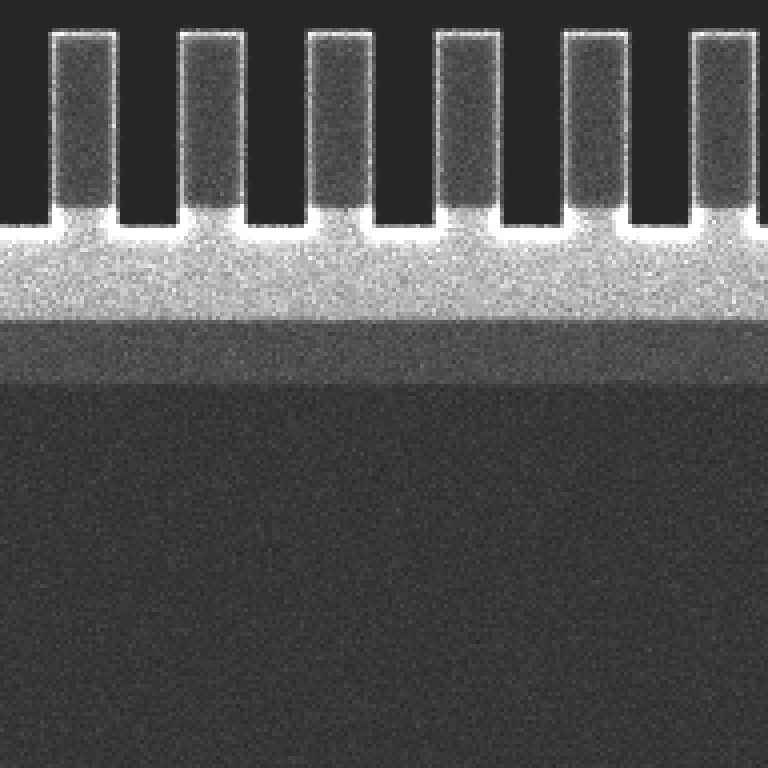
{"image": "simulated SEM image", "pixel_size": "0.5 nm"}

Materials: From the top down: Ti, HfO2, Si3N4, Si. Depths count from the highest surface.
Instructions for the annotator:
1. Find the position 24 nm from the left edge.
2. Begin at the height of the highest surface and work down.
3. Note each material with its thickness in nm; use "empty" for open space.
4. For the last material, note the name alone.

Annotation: empty 98, HfO2 46, Si3N4 32, Si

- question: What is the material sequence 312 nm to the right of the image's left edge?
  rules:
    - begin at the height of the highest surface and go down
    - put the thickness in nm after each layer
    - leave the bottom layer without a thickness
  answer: Ti 88, HfO2 56, Si3N4 32, Si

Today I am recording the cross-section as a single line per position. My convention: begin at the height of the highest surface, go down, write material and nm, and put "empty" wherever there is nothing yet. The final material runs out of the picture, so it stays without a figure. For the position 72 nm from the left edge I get empty 98, HfO2 46, Si3N4 32, Si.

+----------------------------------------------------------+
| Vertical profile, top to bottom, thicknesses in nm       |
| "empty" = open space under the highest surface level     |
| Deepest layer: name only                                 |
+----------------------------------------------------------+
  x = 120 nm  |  Ti 88, HfO2 56, Si3N4 32, Si